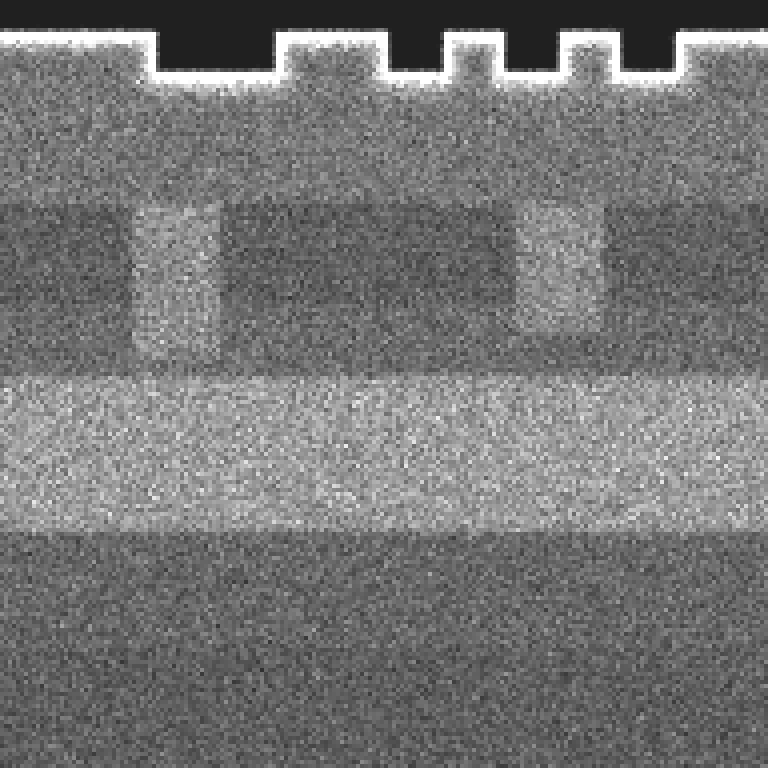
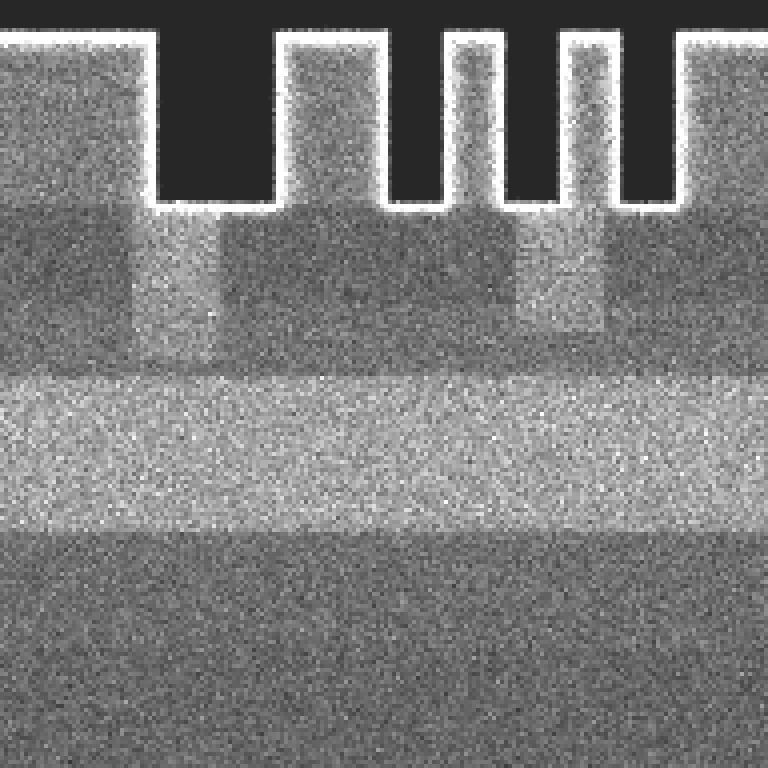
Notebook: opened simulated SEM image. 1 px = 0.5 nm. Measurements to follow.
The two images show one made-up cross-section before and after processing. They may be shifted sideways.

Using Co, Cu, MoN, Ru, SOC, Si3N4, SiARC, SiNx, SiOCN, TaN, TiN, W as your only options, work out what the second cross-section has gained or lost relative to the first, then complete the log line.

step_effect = removed SOC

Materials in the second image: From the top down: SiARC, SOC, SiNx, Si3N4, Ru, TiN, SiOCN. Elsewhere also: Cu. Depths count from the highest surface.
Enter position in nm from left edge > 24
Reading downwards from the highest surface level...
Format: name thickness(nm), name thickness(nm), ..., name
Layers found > SiARC 20, SOC 66, SiNx 50, Si3N4 36, Ru 78, TiN 58, SiOCN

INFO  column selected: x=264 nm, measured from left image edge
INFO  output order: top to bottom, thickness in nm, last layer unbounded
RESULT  empty 86, Cu 64, Si3N4 22, Ru 78, TiN 58, SiOCN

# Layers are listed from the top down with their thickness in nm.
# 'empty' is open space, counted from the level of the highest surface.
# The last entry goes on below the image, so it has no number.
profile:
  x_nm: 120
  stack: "empty 86, SiNx 50, Si3N4 36, Ru 78, TiN 58, SiOCN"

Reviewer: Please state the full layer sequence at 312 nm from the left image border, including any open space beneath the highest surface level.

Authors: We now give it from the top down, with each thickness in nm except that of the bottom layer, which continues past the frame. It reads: empty 86, SiNx 50, Si3N4 36, Ru 78, TiN 58, SiOCN